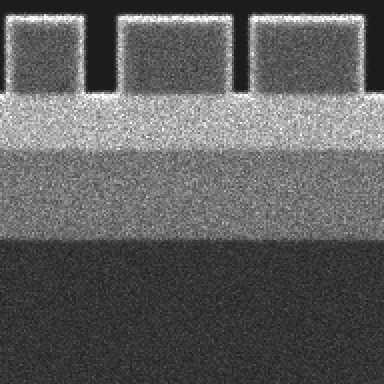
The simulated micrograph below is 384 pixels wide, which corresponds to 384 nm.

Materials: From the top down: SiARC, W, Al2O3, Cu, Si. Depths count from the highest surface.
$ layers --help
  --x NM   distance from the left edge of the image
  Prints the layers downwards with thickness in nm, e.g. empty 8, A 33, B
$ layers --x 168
SiARC 78, W 56, Al2O3 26, Cu 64, Si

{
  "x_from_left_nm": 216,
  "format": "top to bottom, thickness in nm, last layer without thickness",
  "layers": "SiARC 78, W 56, Al2O3 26, Cu 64, Si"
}